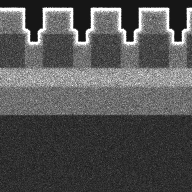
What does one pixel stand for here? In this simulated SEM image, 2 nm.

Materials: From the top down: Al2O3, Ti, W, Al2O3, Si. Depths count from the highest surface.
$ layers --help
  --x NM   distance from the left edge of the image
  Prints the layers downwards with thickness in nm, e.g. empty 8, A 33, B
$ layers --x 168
empty 68, Al2O3 52, W 38, Al2O3 56, Si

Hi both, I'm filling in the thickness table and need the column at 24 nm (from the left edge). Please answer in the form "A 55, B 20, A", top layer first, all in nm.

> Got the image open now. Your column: Al2O3 52, Ti 68, W 38, Al2O3 56, Si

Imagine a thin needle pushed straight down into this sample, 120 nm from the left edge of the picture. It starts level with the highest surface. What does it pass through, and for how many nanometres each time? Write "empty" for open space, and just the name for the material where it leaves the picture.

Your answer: Al2O3 52, Ti 68, W 38, Al2O3 56, Si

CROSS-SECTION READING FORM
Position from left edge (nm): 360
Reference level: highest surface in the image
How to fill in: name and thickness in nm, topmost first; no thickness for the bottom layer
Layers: empty 68, Al2O3 52, W 38, Al2O3 56, Si